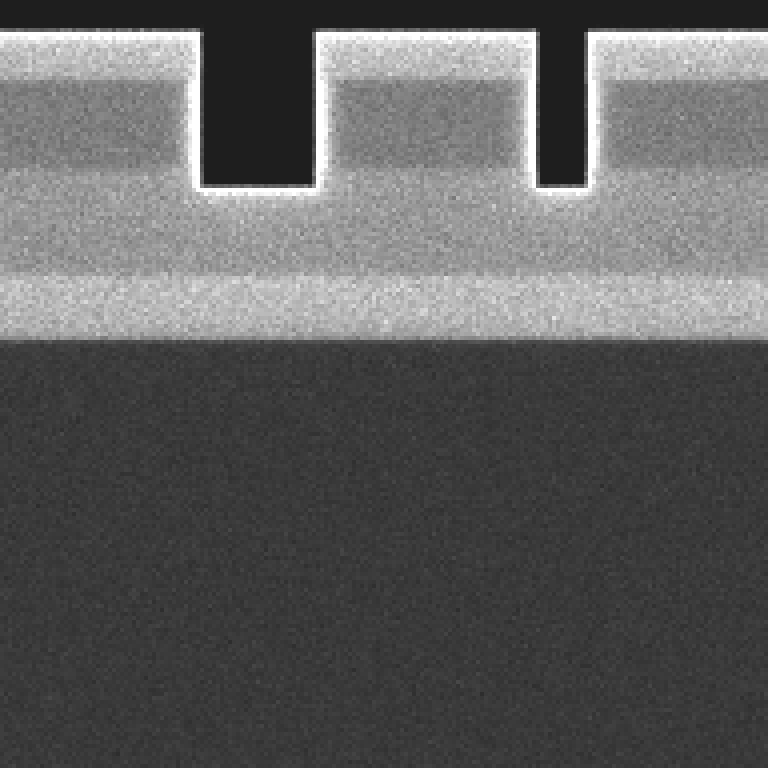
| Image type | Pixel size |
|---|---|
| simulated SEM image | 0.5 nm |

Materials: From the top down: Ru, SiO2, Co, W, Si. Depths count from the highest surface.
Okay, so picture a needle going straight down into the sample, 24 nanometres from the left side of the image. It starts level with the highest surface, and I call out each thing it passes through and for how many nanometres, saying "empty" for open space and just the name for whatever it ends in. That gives Ru 24, SiO2 44, Co 54, W 32, Si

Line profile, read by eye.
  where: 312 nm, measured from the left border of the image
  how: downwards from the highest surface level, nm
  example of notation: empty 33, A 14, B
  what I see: Ru 24, SiO2 44, Co 54, W 32, Si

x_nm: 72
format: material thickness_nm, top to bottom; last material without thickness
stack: Ru 24, SiO2 44, Co 54, W 32, Si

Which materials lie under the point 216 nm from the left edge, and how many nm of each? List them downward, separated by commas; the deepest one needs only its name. Ru 24, SiO2 44, Co 54, W 32, Si